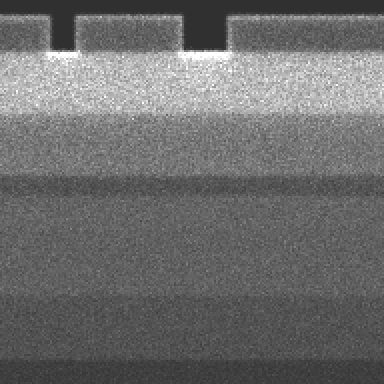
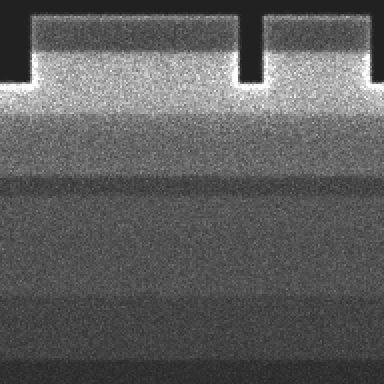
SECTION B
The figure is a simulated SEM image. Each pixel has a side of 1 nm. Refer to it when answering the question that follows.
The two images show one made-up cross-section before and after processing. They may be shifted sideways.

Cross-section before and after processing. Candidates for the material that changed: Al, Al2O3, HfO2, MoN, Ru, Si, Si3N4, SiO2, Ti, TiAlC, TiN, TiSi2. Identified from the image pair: HfO2 (removed).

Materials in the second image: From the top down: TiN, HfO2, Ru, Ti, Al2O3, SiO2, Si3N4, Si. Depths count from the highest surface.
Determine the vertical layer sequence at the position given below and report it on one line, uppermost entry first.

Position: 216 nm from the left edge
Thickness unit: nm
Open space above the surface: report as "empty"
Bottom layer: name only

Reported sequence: TiN 36, HfO2 62, Ru 62, Ti 20, Al2O3 34, SiO2 66, Si3N4 64, Si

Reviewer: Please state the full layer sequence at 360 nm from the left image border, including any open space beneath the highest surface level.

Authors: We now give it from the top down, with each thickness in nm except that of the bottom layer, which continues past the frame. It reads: TiN 36, HfO2 62, Ru 62, Ti 20, Al2O3 34, SiO2 66, Si3N4 64, Si